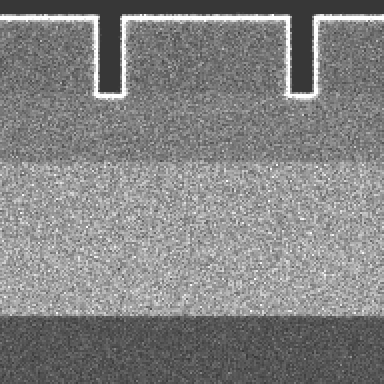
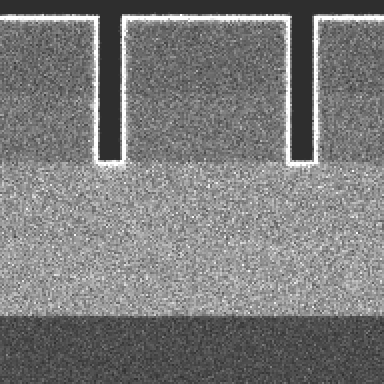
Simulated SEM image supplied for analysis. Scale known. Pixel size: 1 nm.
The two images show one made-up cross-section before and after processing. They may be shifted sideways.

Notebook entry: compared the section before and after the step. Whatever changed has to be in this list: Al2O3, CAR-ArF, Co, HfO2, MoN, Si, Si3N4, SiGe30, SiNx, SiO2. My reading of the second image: Si3N4 removed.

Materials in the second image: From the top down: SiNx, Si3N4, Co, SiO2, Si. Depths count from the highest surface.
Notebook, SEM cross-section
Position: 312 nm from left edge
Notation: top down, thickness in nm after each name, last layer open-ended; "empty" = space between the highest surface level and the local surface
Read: empty 146, Co 78, SiO2 76, Si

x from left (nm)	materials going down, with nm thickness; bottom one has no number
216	SiNx 78, Si3N4 68, Co 78, SiO2 76, Si